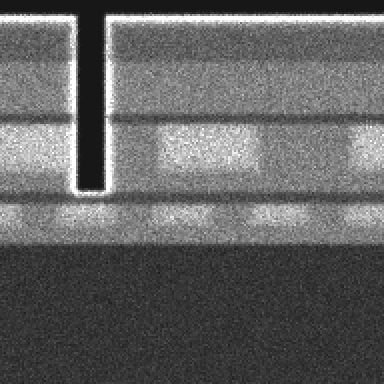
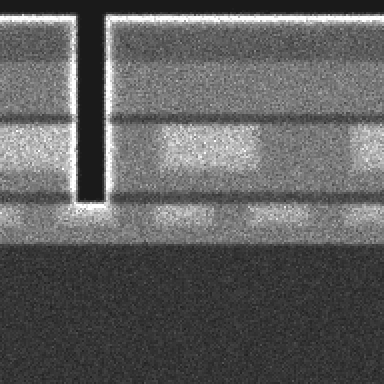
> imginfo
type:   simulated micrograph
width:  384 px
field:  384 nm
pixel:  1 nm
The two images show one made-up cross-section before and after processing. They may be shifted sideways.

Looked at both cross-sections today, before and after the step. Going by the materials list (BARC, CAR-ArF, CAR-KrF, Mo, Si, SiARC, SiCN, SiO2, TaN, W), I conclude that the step removed SiCN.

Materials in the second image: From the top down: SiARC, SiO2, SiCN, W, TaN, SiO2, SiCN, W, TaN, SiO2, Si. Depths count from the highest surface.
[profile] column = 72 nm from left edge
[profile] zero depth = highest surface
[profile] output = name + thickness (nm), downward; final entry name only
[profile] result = SiARC 46, SiO2 52, SiCN 10, SiO2 68, SiCN 12, W 14, TaN 8, SiO2 18, Si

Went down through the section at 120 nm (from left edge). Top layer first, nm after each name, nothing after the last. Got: SiARC 46, SiO2 52, SiCN 10, SiO2 68, SiCN 12, SiO2 40, Si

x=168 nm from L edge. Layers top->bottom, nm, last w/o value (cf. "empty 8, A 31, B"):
SiARC 46, SiO2 52, SiCN 10, W 40, TaN 8, SiO2 20, SiCN 12, W 14, TaN 8, SiO2 18, Si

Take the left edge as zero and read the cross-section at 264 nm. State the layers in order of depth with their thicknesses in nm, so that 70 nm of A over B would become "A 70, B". SiARC 46, SiO2 52, SiCN 10, SiO2 68, SiCN 12, W 14, TaN 8, SiO2 18, Si